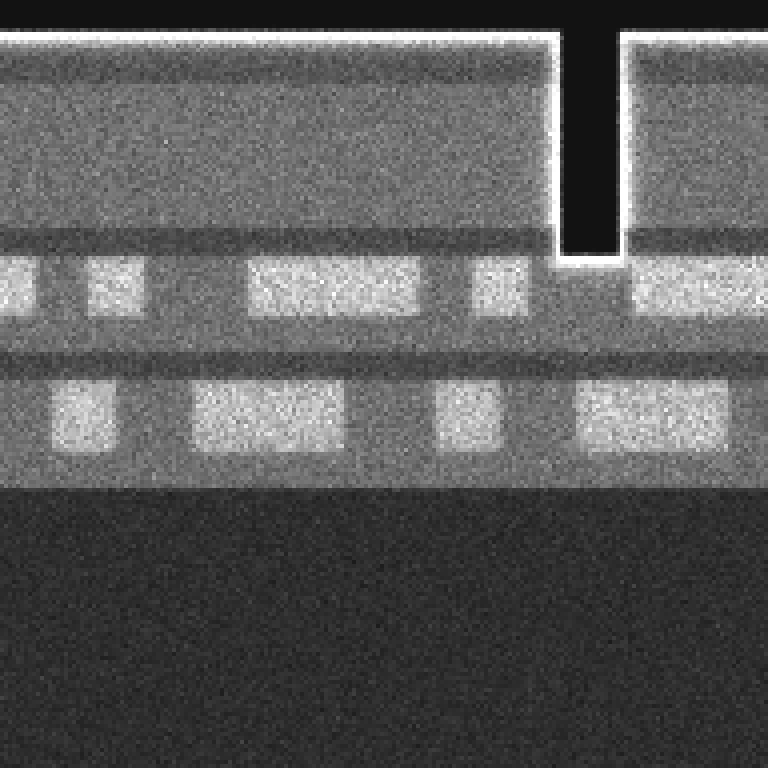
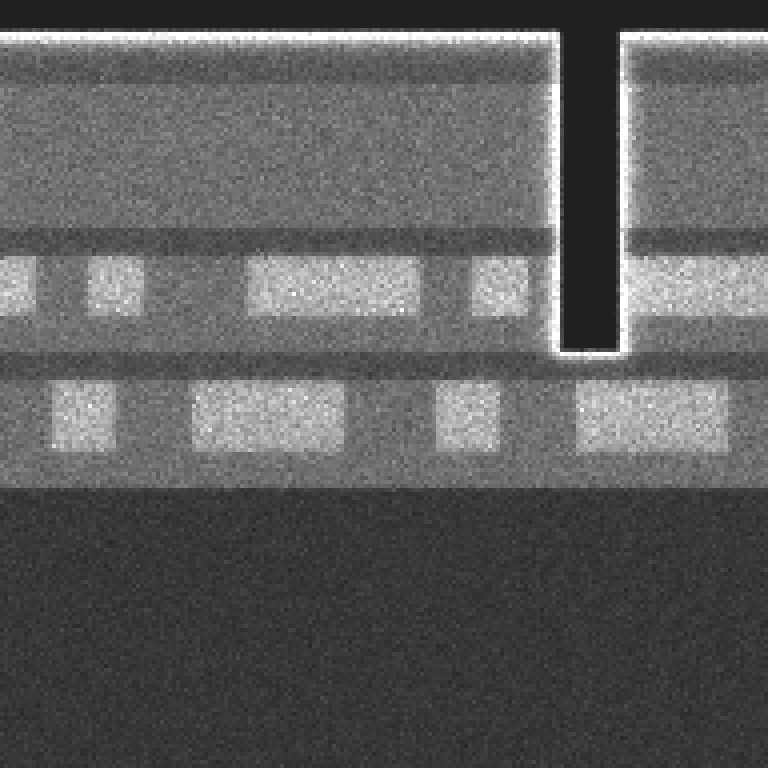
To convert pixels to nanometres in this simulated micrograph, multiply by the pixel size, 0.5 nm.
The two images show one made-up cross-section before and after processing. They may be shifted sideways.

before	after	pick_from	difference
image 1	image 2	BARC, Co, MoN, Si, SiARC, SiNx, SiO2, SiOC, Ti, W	SiO2 removed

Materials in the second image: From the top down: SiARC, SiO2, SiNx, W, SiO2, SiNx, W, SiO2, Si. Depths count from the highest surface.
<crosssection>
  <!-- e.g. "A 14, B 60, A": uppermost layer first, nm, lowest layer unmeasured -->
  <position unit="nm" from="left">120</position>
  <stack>SiARC 26, SiO2 72, SiNx 14, SiO2 48, SiNx 14, W 36, SiO2 18, Si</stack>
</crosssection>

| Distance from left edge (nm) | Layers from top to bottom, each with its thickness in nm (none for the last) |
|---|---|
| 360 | SiARC 26, SiO2 72, SiNx 14, W 30, SiO2 18, SiNx 14, W 36, SiO2 18, Si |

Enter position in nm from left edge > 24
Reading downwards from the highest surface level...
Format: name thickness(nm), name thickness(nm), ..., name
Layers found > SiARC 26, SiO2 72, SiNx 14, SiO2 48, SiNx 14, SiO2 54, Si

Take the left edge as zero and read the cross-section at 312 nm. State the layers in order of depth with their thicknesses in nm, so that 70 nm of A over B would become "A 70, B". SiARC 26, SiO2 72, SiNx 14, SiO2 48, SiNx 14, W 36, SiO2 18, Si